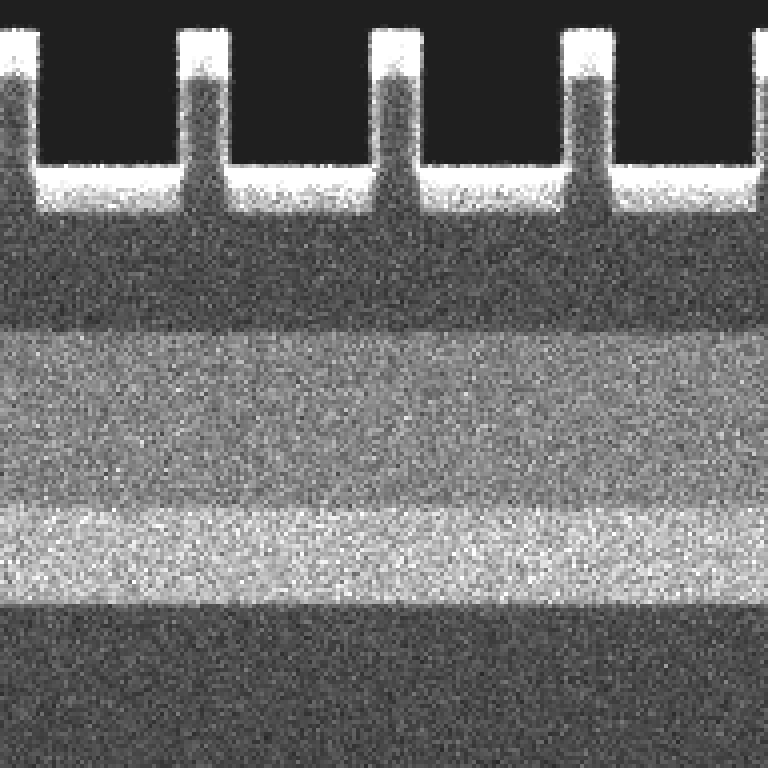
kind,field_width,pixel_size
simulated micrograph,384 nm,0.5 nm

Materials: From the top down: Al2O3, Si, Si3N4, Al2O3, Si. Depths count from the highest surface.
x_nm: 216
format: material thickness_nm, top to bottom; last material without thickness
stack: empty 68, Al2O3 22, Si 60, Si3N4 88, Al2O3 48, Si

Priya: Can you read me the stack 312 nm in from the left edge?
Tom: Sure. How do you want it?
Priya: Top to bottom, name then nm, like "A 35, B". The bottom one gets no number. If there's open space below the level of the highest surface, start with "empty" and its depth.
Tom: empty 68, Al2O3 22, Si 60, Si3N4 88, Al2O3 48, Si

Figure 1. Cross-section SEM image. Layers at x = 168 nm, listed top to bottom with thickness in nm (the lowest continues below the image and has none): empty 68, Al2O3 22, Si 60, Si3N4 88, Al2O3 48, Si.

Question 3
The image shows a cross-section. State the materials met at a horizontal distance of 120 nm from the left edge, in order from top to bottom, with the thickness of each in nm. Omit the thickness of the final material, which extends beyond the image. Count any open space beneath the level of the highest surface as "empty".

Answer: empty 68, Al2O3 22, Si 60, Si3N4 88, Al2O3 48, Si